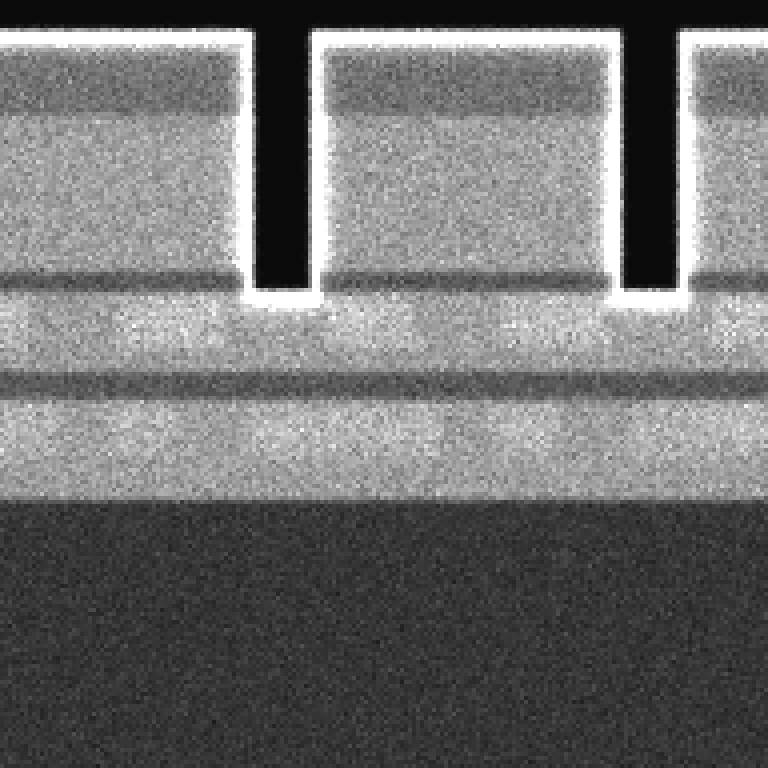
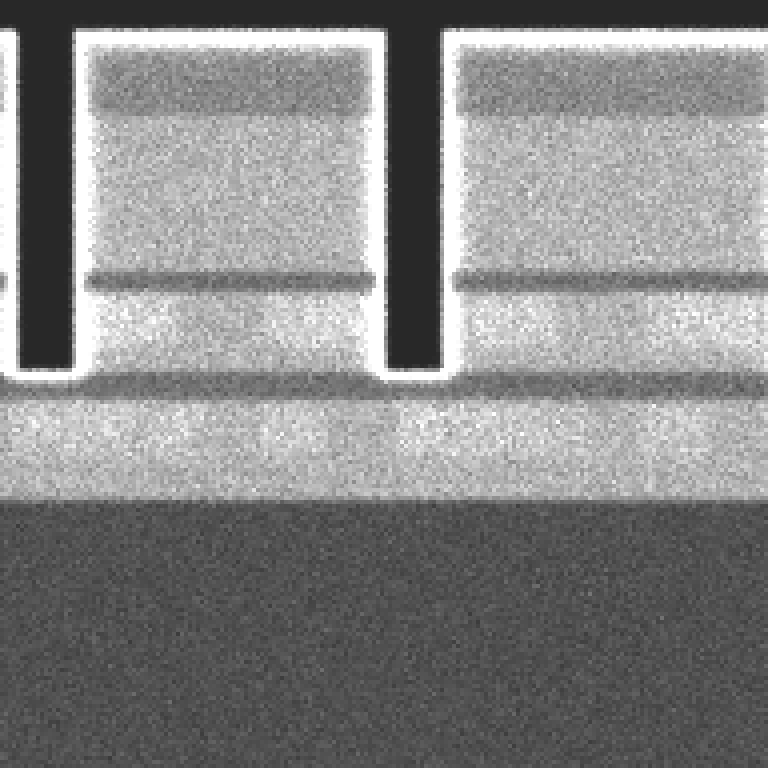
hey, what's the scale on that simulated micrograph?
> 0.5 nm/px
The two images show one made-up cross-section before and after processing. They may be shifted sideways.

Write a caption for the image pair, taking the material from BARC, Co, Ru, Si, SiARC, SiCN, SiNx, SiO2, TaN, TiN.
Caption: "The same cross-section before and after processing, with SiO2 removed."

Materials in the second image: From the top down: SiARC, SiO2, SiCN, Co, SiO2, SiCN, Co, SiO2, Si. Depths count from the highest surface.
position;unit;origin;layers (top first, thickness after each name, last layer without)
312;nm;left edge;SiARC 42, SiO2 78, SiCN 10, SiO2 40, SiCN 14, SiO2 50, Si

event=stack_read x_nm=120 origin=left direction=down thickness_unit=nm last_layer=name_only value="SiARC 42, SiO2 78, SiCN 10, SiO2 40, SiCN 14, SiO2 50, Si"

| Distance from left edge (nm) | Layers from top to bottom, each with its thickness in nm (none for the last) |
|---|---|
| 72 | SiARC 42, SiO2 78, SiCN 10, Co 28, SiO2 12, SiCN 14, Co 28, SiO2 22, Si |